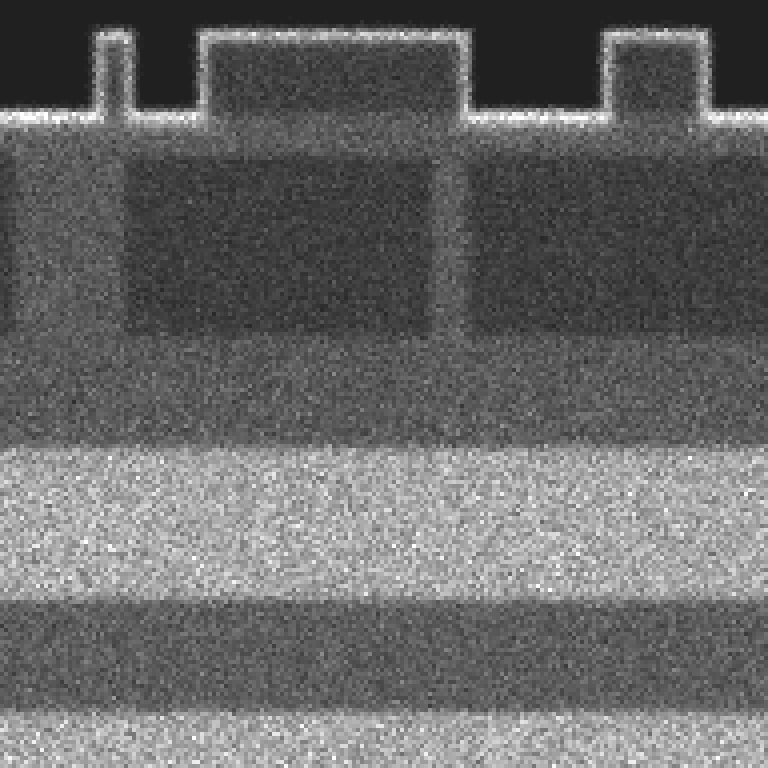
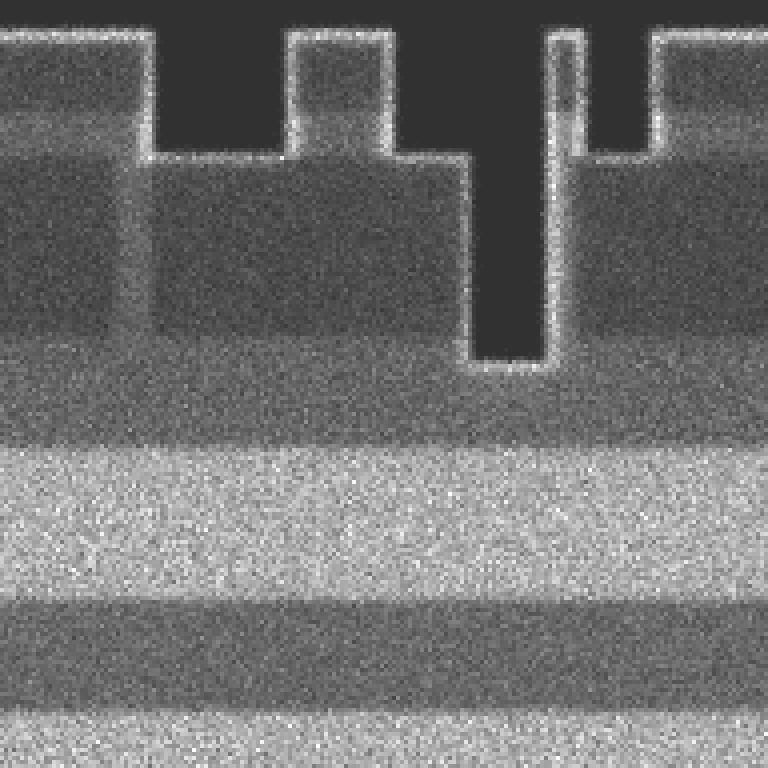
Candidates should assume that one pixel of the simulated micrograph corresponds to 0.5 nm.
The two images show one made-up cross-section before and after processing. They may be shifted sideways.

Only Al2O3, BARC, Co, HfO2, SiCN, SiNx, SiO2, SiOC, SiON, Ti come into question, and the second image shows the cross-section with SiO2 removed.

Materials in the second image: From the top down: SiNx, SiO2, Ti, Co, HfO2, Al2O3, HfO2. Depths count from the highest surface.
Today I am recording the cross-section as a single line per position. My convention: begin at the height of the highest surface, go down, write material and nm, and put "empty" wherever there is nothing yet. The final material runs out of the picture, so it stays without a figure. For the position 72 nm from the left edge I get SiNx 40, SiO2 126, Co 42, HfO2 76, Al2O3 56, HfO2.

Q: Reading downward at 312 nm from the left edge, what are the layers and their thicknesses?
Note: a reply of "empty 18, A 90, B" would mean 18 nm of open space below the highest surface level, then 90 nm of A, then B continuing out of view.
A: empty 62, Ti 90, Co 56, HfO2 76, Al2O3 56, HfO2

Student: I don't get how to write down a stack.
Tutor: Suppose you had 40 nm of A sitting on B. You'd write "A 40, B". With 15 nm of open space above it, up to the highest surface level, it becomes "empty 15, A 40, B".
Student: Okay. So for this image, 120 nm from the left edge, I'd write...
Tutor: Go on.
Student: empty 62, Ti 90, Co 56, HfO2 76, Al2O3 56, HfO2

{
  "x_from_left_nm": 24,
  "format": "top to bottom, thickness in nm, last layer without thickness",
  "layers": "SiNx 40, SiO2 22, Ti 90, Co 56, HfO2 76, Al2O3 56, HfO2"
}